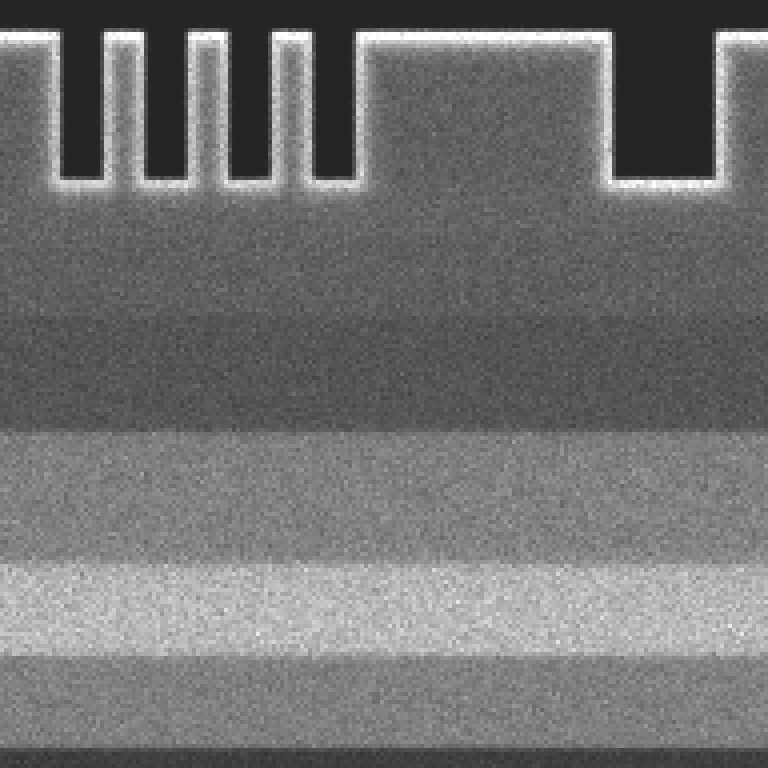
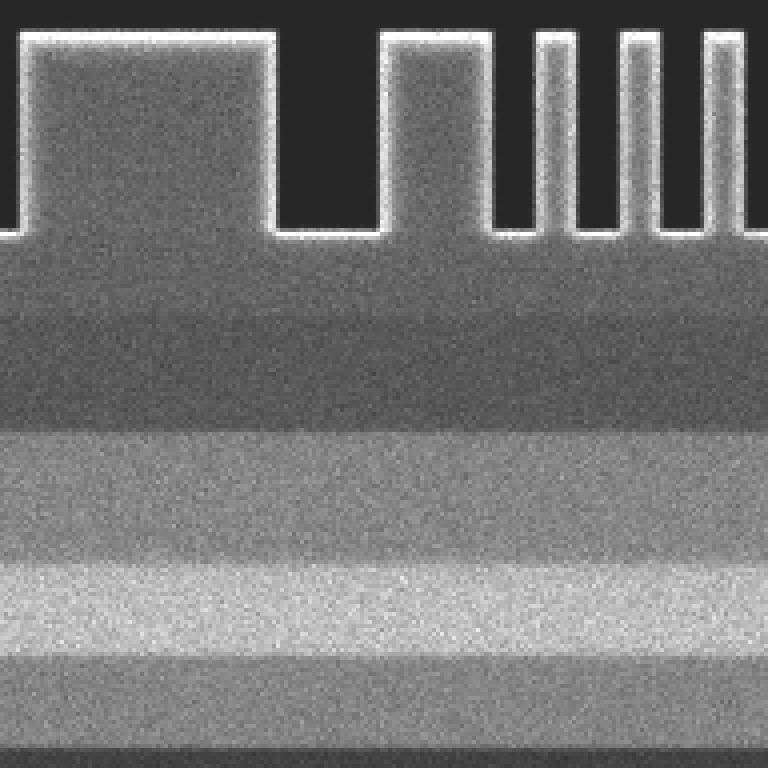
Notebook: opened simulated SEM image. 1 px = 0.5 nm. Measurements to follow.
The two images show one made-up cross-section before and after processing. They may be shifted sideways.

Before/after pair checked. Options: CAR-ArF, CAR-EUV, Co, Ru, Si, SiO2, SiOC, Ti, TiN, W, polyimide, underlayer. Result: removed underlayer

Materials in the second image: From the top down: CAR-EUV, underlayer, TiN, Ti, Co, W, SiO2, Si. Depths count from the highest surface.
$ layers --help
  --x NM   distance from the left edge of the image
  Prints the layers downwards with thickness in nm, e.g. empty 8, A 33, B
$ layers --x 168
empty 100, TiN 42, Ti 58, Co 66, W 46, SiO2 46, Si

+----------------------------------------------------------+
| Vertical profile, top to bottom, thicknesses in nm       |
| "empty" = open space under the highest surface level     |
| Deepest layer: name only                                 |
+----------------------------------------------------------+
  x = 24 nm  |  CAR-EUV 74, underlayer 26, TiN 42, Ti 58, Co 66, W 46, SiO2 46, Si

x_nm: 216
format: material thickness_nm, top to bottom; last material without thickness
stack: CAR-EUV 74, underlayer 26, TiN 42, Ti 58, Co 66, W 46, SiO2 46, Si